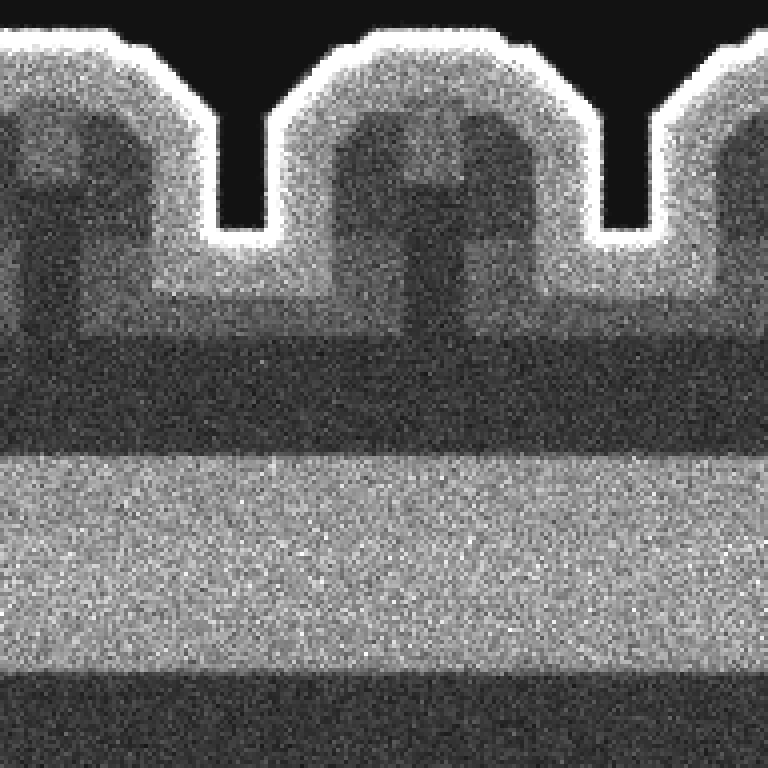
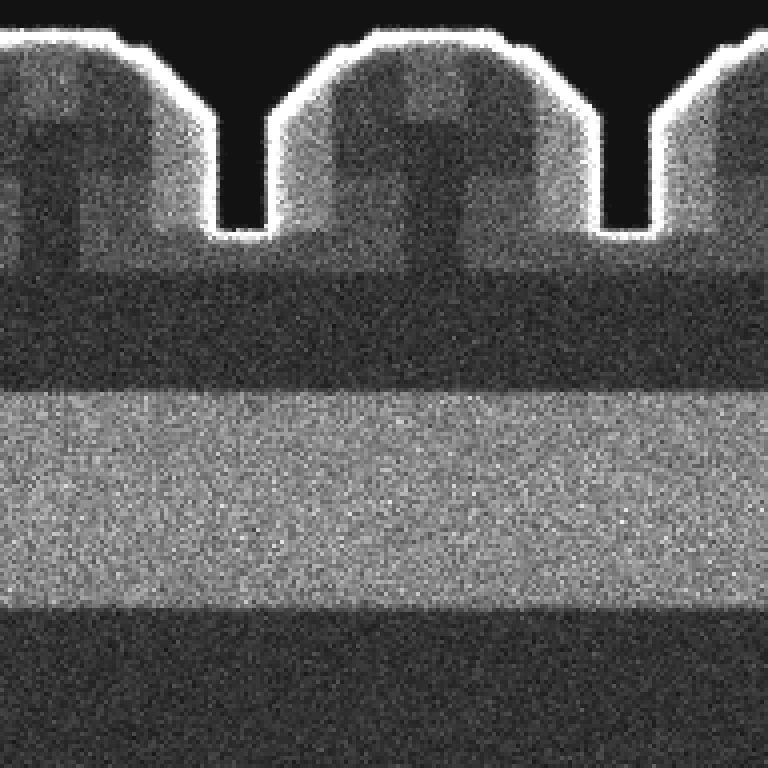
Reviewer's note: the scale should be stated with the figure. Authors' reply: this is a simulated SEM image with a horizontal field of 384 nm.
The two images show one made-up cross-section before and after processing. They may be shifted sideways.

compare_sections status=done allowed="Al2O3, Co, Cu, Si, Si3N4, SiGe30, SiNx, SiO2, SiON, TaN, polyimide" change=removed material="SiO2"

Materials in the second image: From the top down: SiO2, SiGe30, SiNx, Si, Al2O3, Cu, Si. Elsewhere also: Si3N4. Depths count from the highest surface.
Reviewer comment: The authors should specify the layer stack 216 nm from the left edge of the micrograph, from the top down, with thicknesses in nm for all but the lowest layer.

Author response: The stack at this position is Si3N4 44, Si 136, Al2O3 40, Cu 68, Si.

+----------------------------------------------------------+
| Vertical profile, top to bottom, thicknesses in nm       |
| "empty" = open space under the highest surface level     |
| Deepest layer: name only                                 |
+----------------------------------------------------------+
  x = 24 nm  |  Si3N4 44, Si 136, Al2O3 40, Cu 68, Si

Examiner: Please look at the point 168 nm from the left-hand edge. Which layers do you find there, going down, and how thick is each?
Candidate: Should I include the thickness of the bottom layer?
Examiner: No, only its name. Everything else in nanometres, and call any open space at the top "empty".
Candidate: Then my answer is empty 8, SiO2 16, SiGe30 48, SiNx 48, Si 60, Al2O3 40, Cu 68, Si